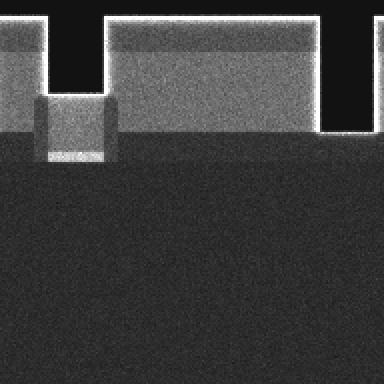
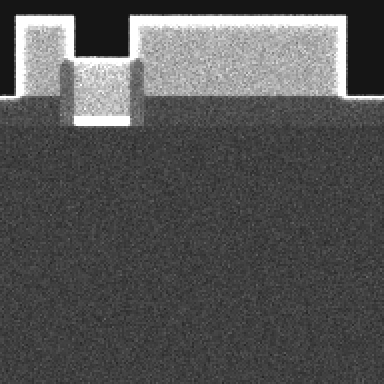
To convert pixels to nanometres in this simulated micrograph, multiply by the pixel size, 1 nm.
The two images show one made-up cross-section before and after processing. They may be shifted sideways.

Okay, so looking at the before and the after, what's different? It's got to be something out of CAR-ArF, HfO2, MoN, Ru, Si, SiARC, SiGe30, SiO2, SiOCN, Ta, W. SiARC, removed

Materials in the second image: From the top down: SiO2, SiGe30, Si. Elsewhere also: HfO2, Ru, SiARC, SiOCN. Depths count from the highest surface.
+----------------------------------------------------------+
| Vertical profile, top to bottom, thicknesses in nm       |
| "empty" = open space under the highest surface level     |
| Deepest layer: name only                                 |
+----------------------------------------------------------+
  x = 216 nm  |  SiO2 80, SiGe30 30, Si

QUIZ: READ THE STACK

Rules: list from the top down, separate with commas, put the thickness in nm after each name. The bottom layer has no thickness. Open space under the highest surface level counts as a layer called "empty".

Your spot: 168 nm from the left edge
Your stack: SiO2 80, SiGe30 30, Si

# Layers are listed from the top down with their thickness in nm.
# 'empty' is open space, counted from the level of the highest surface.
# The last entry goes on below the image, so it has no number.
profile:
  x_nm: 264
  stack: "SiO2 80, SiGe30 30, Si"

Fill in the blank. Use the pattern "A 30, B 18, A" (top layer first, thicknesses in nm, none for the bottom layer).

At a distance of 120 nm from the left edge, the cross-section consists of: empty 42, Ru 58, HfO2 10, Si